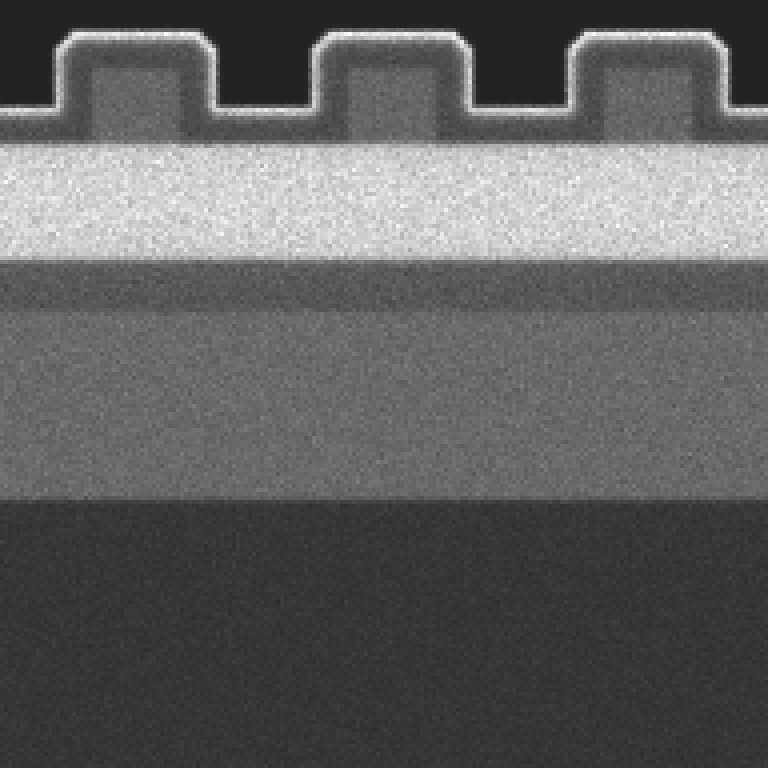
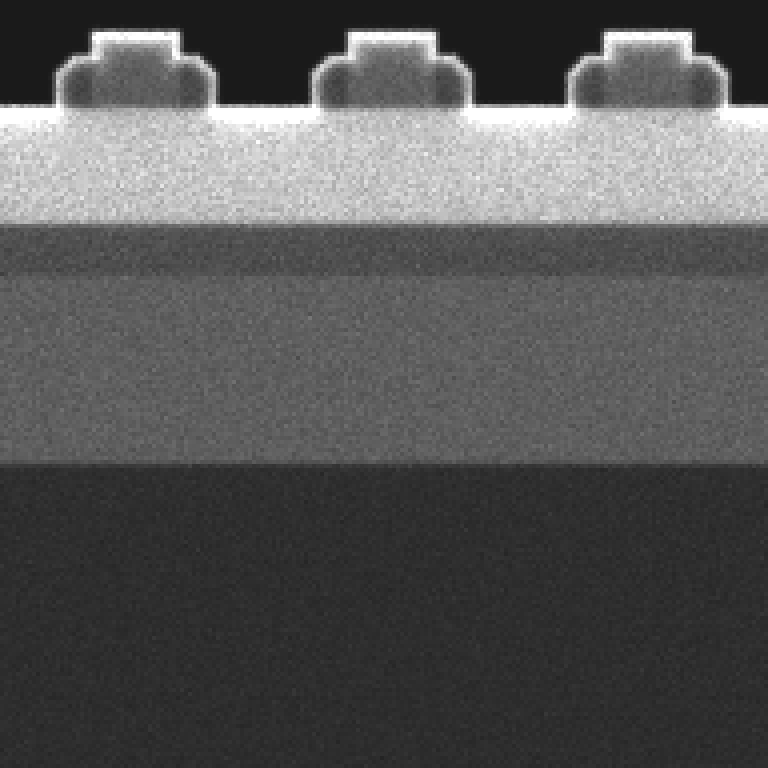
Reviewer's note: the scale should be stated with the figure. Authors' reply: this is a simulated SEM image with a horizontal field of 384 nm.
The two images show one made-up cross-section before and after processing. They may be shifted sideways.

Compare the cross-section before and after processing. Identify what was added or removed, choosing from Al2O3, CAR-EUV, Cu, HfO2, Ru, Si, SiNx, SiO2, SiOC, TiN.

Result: SiNx removed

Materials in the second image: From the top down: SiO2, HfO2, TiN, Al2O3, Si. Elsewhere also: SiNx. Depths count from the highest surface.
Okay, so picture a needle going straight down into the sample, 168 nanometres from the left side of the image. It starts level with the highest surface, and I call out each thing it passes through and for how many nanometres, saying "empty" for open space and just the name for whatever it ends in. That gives empty 12, SiNx 26, HfO2 58, TiN 26, Al2O3 94, Si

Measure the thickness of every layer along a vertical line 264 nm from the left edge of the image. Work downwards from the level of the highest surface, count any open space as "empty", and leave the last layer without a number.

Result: empty 38, HfO2 58, TiN 26, Al2O3 94, Si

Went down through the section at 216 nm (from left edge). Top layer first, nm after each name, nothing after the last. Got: SiO2 38, HfO2 58, TiN 26, Al2O3 94, Si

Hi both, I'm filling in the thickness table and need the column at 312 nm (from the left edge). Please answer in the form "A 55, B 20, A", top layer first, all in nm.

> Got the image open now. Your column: SiO2 38, HfO2 58, TiN 26, Al2O3 94, Si